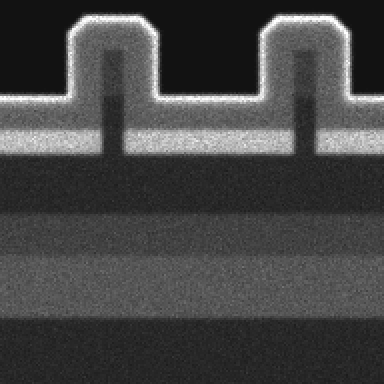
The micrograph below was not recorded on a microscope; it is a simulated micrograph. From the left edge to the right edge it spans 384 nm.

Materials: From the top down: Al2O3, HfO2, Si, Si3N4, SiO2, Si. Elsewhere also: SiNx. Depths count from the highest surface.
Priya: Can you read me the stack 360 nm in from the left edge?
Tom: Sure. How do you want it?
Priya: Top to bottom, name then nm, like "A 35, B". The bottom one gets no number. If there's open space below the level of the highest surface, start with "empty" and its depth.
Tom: empty 80, Al2O3 34, HfO2 24, Si 60, Si3N4 42, SiO2 62, Si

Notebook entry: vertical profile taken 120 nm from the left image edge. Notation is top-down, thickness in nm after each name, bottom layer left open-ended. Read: Al2O3 34, SiNx 46, Si 118, Si3N4 42, SiO2 62, Si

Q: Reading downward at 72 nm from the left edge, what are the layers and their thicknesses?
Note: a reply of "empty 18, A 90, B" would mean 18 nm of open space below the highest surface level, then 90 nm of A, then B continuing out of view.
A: empty 12, Al2O3 102, HfO2 24, Si 60, Si3N4 42, SiO2 62, Si